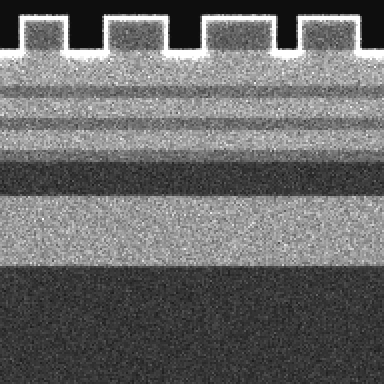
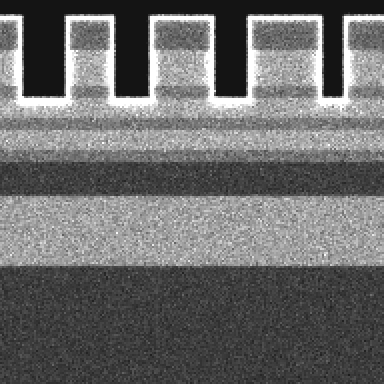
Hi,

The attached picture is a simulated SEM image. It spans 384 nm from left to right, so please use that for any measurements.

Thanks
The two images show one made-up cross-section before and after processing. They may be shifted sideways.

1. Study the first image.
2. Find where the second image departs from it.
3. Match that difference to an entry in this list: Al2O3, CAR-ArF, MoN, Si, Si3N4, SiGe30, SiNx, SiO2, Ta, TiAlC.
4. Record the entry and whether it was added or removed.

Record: Al2O3 and Si3N4 / removed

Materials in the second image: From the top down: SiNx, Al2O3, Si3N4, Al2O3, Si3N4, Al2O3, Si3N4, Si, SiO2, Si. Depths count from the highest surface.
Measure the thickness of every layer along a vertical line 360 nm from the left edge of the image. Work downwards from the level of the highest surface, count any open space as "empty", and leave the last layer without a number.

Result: SiNx 34, Al2O3 36, Si3N4 12, Al2O3 20, Si3N4 12, Al2O3 20, Si3N4 12, Si 34, SiO2 70, Si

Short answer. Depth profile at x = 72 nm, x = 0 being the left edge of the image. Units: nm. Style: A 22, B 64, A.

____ SiNx 34, Al2O3 36, Si3N4 12, Al2O3 20, Si3N4 12, Al2O3 20, Si3N4 12, Si 34, SiO2 70, Si